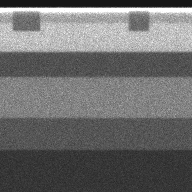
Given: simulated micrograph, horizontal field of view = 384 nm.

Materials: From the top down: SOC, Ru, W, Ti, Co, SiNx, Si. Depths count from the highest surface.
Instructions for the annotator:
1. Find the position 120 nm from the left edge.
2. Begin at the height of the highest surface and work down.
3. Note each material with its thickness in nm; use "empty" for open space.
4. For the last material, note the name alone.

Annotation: SOC 6, Ru 24, W 58, Ti 50, Co 82, SiNx 64, Si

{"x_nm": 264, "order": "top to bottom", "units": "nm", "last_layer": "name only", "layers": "SOC 46, W 42, Ti 50, Co 82, SiNx 64, Si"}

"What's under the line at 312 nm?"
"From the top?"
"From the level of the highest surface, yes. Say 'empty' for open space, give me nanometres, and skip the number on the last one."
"SOC 6, Ru 24, W 58, Ti 50, Co 82, SiNx 64, Si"